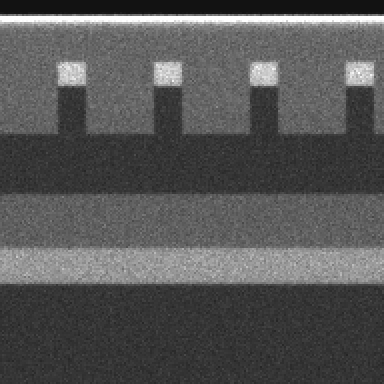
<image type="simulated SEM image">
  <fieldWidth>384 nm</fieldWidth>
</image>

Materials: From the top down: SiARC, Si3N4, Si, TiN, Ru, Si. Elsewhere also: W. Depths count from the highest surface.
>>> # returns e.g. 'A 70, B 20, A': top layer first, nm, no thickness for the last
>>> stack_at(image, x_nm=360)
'SiARC 46, W 24, Si 108, TiN 54, Ru 36, Si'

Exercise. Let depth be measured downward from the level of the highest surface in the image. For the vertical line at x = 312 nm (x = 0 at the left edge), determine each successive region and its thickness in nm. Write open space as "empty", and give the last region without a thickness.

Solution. SiARC 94, Si3N4 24, Si 60, TiN 54, Ru 36, Si